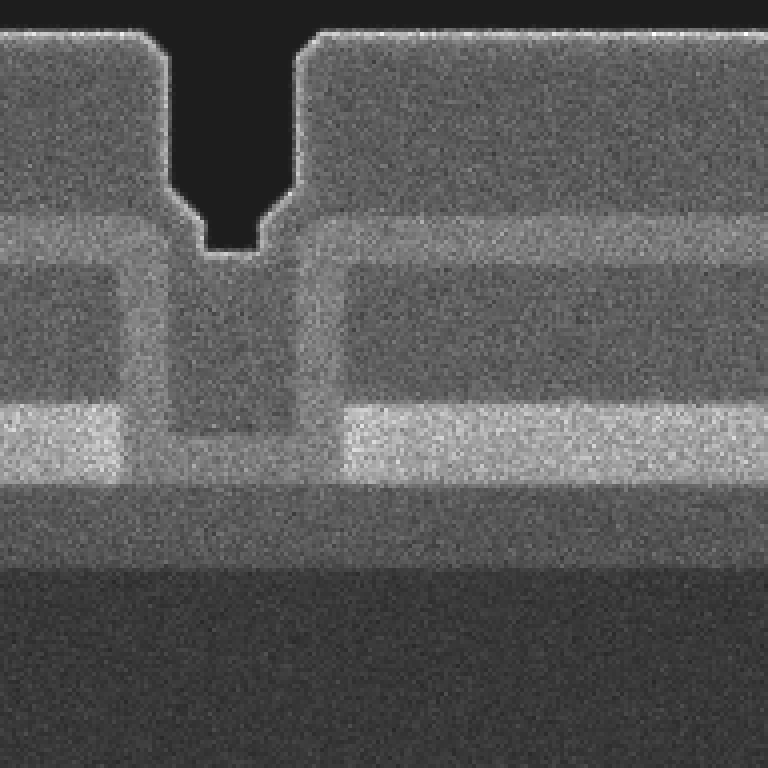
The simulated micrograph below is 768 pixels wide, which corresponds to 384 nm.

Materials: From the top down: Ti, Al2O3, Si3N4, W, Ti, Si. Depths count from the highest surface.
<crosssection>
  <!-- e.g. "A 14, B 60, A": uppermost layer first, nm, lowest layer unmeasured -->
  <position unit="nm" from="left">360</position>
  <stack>Ti 92, Al2O3 24, Si3N4 70, W 40, Ti 42, Si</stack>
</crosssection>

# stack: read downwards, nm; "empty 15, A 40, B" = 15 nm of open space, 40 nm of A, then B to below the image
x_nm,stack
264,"Ti 92, Al2O3 24, Si3N4 70, W 40, Ti 42, Si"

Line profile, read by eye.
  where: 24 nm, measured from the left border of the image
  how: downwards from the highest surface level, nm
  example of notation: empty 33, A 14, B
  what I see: Ti 92, Al2O3 24, Si3N4 70, W 40, Ti 42, Si